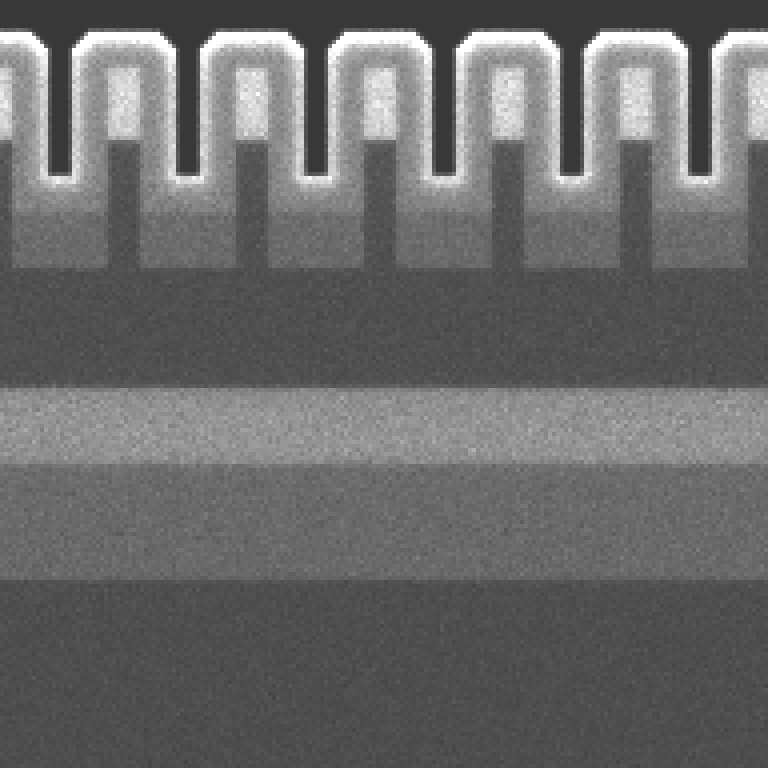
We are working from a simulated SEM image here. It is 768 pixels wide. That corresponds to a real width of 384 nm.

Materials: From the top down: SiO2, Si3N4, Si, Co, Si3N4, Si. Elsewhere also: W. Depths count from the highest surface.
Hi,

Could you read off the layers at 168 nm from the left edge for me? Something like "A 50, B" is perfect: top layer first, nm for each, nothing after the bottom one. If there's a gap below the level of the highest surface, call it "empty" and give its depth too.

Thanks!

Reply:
empty 4, SiO2 86, Si3N4 28, Si 60, Co 38, Si3N4 58, Si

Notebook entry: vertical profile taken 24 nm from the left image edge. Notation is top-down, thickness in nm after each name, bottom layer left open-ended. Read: empty 72, SiO2 18, Si3N4 28, Si 60, Co 38, Si3N4 58, Si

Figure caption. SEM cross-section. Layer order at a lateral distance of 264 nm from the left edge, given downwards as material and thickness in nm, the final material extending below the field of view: SiO2 90, Si3N4 28, Si 60, Co 38, Si3N4 58, Si